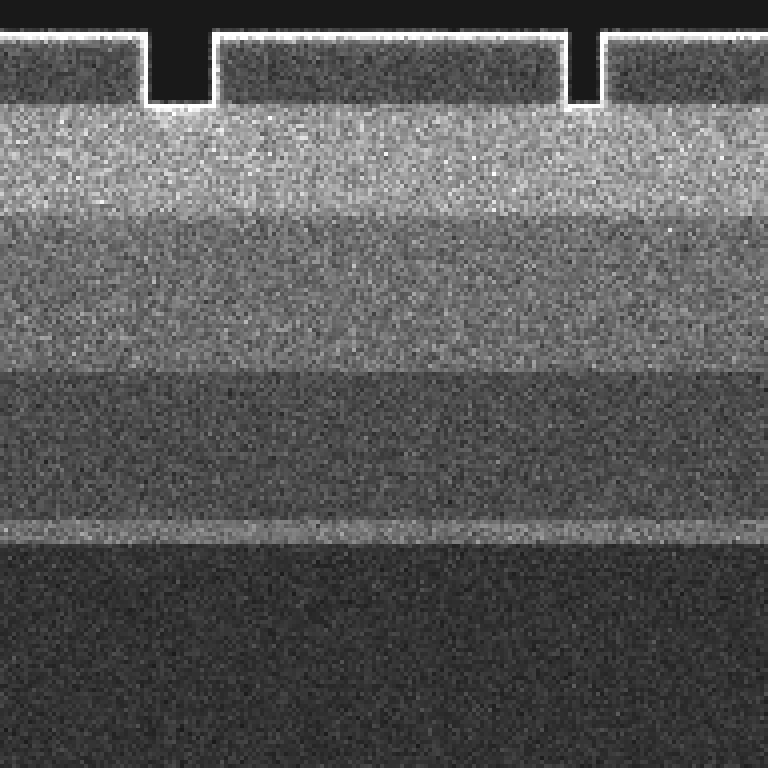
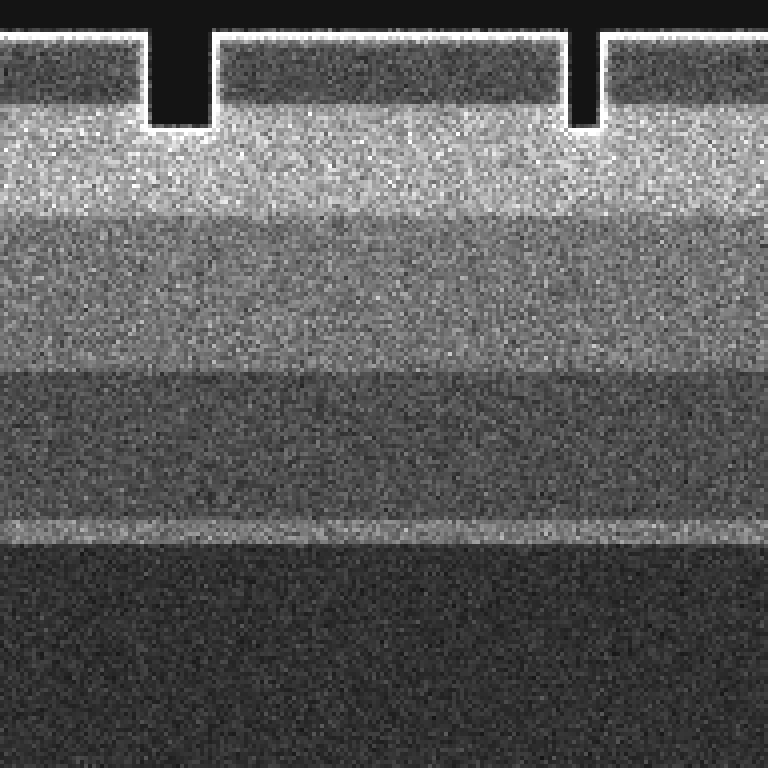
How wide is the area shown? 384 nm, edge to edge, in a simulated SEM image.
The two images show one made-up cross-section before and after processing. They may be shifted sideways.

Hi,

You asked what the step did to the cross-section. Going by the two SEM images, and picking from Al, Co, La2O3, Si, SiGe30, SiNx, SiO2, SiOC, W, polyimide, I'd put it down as W, removed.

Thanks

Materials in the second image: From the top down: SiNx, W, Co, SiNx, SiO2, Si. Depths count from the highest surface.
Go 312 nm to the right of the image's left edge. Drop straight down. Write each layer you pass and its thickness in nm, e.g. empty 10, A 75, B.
SiNx 36, W 56, Co 78, SiNx 74, SiO2 12, Si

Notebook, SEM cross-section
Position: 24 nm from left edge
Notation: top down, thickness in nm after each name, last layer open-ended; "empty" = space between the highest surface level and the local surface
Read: SiNx 36, W 56, Co 78, SiNx 74, SiO2 12, Si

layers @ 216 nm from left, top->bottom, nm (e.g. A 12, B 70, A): SiNx 36, W 56, Co 78, SiNx 74, SiO2 12, Si